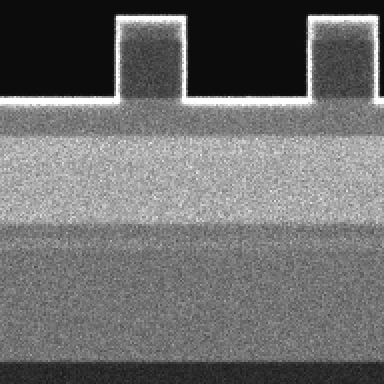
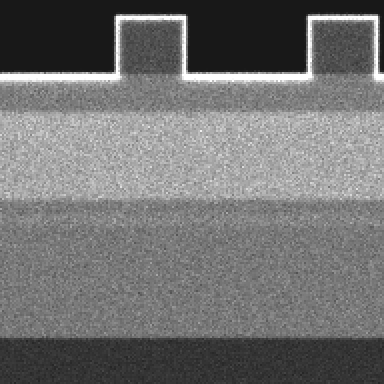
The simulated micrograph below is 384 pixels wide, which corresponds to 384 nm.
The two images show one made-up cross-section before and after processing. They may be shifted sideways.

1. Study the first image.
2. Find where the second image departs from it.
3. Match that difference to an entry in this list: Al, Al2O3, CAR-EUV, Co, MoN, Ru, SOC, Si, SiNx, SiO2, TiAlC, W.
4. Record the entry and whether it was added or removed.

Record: SOC / removed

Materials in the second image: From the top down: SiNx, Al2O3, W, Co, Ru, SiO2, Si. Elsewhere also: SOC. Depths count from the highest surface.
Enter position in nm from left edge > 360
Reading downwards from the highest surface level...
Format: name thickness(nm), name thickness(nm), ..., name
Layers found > SiNx 58, Al2O3 38, W 88, Co 14, Ru 12, SiO2 112, Si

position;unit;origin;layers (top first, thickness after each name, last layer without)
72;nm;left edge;empty 58, Al2O3 38, W 88, Co 14, Ru 12, SiO2 112, Si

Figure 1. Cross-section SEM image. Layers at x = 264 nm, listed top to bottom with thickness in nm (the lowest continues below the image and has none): empty 58, Al2O3 38, W 88, Co 14, Ru 12, SiO2 112, Si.